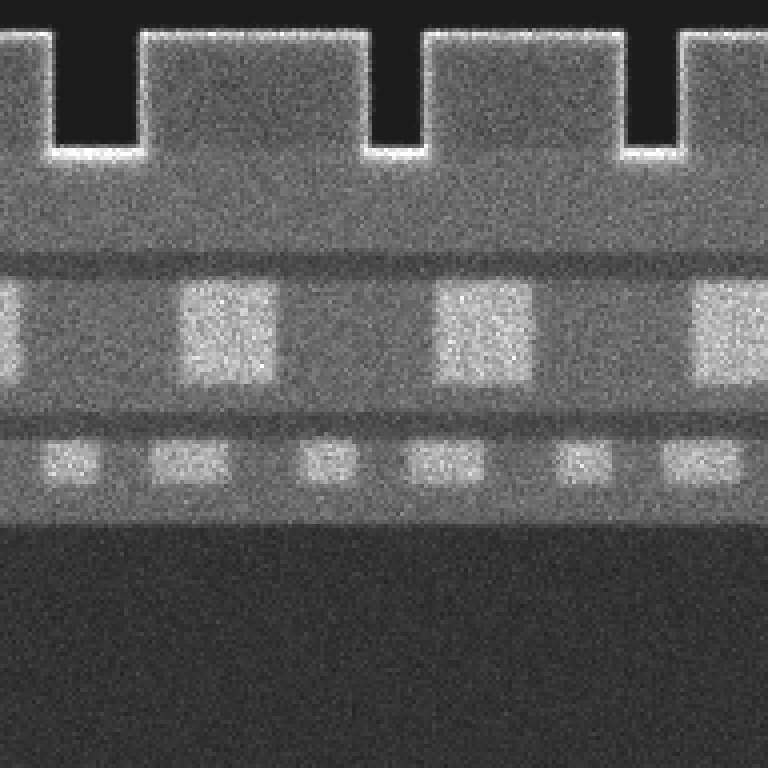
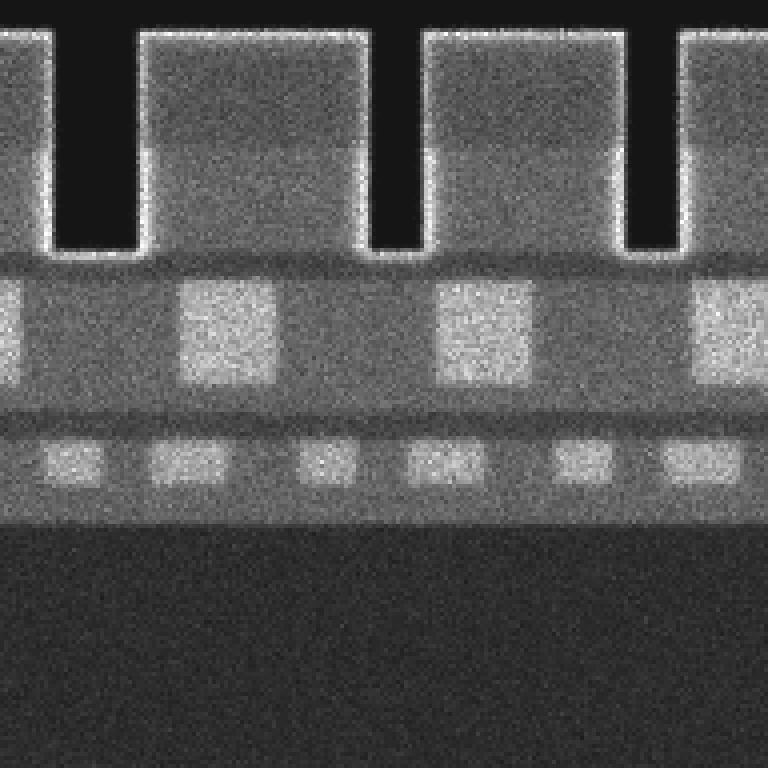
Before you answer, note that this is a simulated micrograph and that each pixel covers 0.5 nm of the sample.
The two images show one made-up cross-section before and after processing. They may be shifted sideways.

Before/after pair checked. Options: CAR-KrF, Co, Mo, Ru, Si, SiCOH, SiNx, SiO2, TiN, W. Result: removed SiO2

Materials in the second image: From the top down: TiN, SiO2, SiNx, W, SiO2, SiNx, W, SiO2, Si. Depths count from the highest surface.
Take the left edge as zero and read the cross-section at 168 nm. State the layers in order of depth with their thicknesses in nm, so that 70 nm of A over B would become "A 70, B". TiN 58, SiO2 52, SiNx 14, SiO2 66, SiNx 14, W 22, SiO2 20, Si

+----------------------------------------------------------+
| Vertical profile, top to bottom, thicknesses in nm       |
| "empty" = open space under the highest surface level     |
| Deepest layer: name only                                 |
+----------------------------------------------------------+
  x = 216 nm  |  TiN 58, SiO2 52, SiNx 14, SiO2 66, SiNx 14, W 22, SiO2 20, Si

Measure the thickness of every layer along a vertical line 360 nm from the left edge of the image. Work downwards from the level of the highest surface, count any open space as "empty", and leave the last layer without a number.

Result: TiN 58, SiO2 52, SiNx 14, W 52, SiO2 14, SiNx 14, W 22, SiO2 20, Si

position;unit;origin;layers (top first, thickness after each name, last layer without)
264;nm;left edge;TiN 58, SiO2 52, SiNx 14, W 52, SiO2 14, SiNx 14, SiO2 42, Si